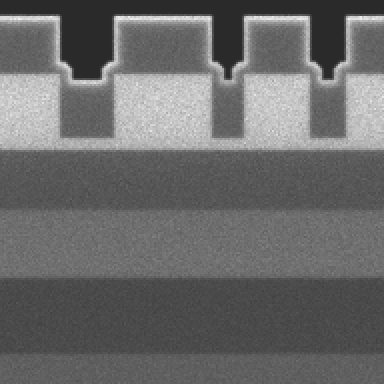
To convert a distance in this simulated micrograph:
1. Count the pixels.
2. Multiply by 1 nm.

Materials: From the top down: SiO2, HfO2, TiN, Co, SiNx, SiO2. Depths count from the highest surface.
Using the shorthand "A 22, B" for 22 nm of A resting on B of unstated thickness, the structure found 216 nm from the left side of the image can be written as empty 46, SiO2 76, HfO2 12, TiN 60, Co 68, SiNx 76, SiO2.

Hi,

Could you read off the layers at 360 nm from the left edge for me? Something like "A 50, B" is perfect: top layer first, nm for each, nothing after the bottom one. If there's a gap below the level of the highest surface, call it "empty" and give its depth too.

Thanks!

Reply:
SiO2 58, HfO2 76, TiN 60, Co 68, SiNx 76, SiO2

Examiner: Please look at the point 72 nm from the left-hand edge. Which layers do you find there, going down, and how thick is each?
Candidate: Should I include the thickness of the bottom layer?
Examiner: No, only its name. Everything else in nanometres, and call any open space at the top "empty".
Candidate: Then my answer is empty 64, SiO2 58, HfO2 12, TiN 60, Co 68, SiNx 76, SiO2